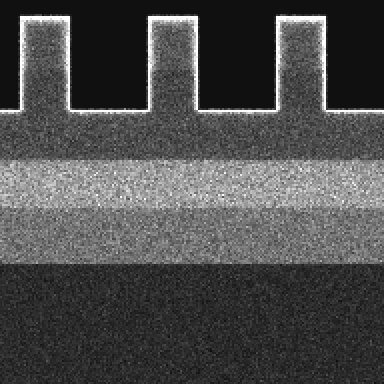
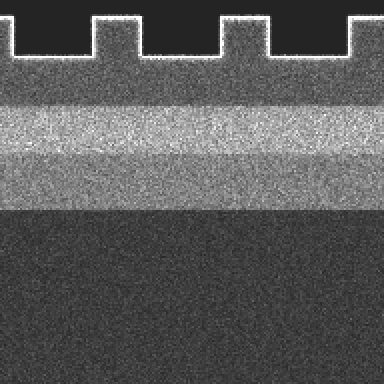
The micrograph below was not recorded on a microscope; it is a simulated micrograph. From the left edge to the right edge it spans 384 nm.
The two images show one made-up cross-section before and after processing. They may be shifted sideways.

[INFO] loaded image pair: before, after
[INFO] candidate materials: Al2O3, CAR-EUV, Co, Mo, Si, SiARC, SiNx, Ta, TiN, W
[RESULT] removed SiARC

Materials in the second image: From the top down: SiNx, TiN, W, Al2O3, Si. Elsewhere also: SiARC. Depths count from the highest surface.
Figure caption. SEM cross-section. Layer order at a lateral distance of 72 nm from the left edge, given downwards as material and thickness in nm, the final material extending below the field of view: empty 40, TiN 50, W 48, Al2O3 56, Si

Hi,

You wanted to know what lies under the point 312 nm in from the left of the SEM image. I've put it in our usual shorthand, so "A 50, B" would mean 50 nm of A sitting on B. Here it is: empty 40, TiN 50, W 48, Al2O3 56, Si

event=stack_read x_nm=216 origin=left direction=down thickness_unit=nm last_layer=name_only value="empty 40, TiN 50, W 48, Al2O3 56, Si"